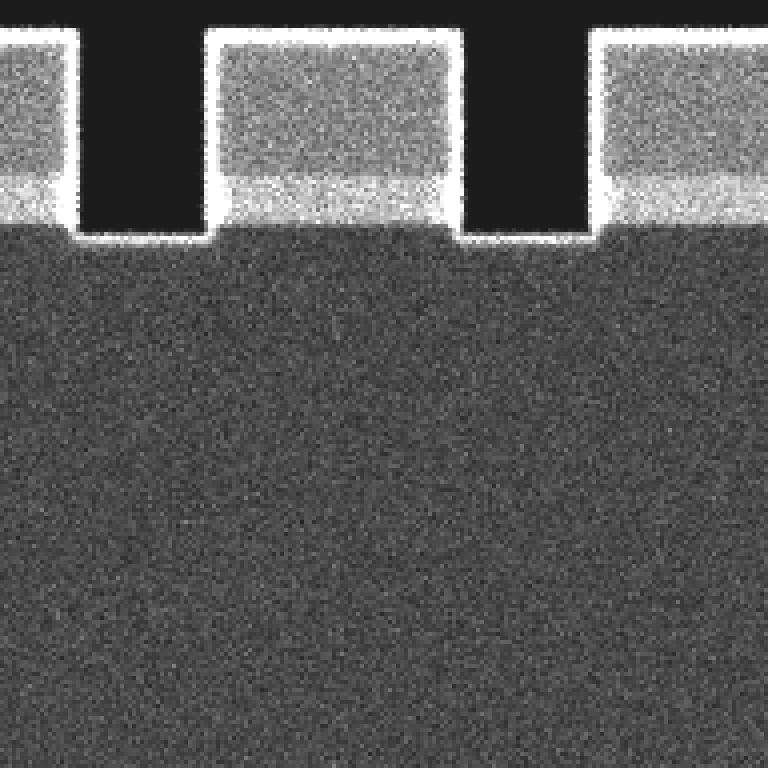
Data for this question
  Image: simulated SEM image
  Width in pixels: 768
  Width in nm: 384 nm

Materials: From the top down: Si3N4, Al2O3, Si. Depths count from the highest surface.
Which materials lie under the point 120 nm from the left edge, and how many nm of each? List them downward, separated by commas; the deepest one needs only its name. Si3N4 72, Al2O3 24, Si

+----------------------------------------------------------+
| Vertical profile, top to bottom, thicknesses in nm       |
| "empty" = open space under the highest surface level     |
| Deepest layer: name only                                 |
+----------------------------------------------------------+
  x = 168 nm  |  Si3N4 72, Al2O3 24, Si